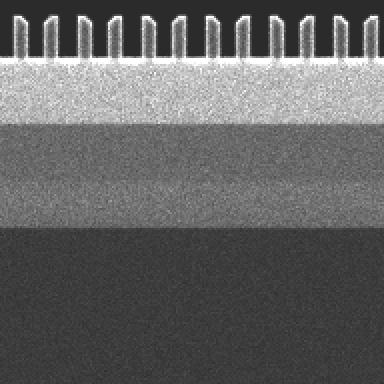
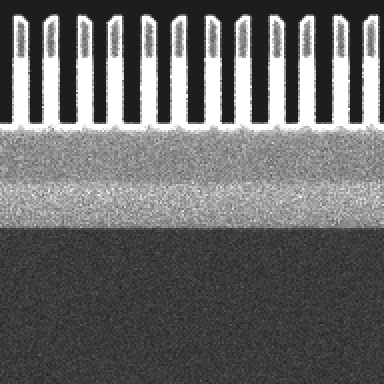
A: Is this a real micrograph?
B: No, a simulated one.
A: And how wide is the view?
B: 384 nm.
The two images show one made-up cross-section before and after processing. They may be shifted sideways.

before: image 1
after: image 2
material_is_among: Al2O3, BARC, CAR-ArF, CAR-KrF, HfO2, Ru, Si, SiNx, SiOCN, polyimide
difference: HfO2, removed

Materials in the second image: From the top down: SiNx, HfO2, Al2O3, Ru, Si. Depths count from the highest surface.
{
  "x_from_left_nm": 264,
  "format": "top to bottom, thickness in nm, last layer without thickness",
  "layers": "empty 108, Al2O3 58, Ru 46, Si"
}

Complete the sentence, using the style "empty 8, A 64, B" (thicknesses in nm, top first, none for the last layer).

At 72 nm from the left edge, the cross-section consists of empty 108, Al2O3 58, Ru 46, Si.